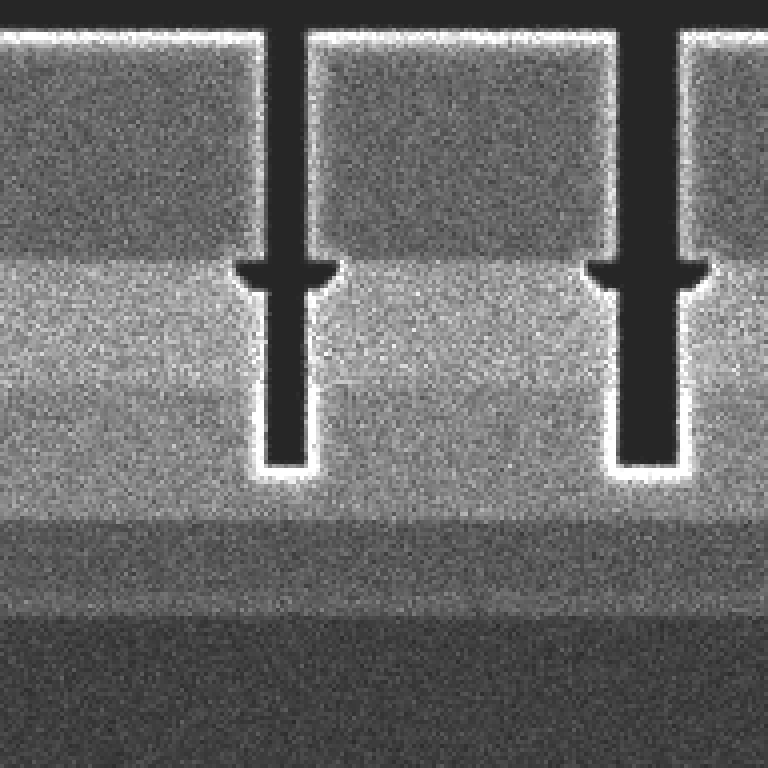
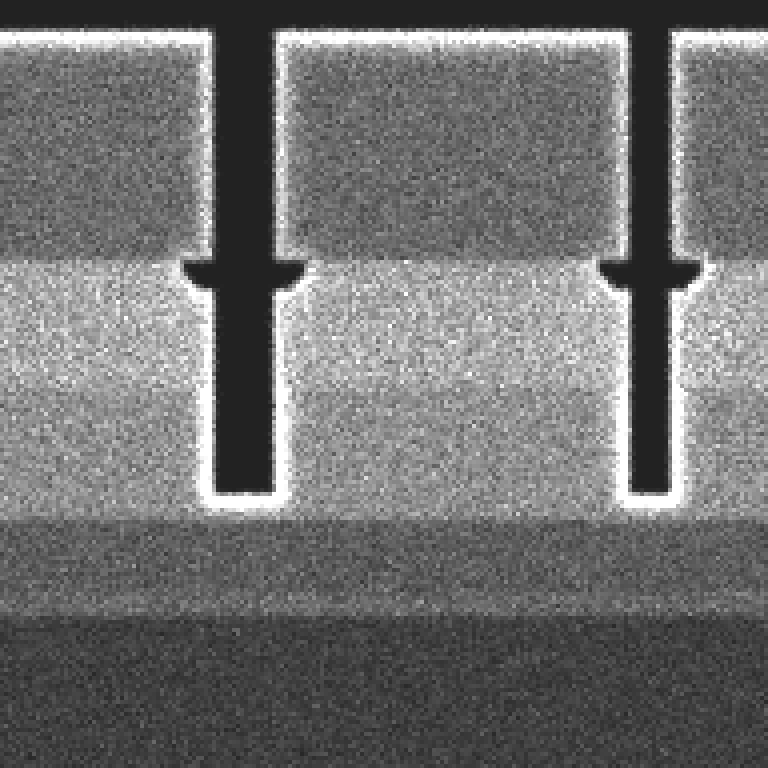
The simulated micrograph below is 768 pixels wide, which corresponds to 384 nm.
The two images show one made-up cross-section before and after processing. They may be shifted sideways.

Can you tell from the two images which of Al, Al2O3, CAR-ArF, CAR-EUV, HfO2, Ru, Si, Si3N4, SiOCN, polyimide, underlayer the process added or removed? Yes, it removed Al2O3.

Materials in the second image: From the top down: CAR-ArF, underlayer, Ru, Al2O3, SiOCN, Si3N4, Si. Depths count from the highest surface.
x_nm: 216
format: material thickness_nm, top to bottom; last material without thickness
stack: CAR-ArF 72, underlayer 42, Ru 64, Al2O3 66, SiOCN 36, Si3N4 12, Si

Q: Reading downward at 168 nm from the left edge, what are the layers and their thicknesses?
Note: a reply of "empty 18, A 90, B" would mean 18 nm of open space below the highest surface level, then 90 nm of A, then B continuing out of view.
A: CAR-ArF 72, underlayer 42, Ru 64, Al2O3 66, SiOCN 36, Si3N4 12, Si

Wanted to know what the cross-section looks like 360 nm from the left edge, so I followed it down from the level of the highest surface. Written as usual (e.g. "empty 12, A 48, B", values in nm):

CAR-ArF 72, underlayer 42, Ru 64, Al2O3 66, SiOCN 36, Si3N4 12, Si